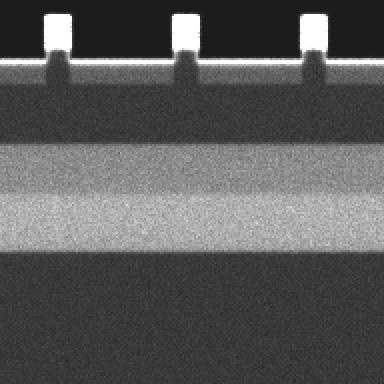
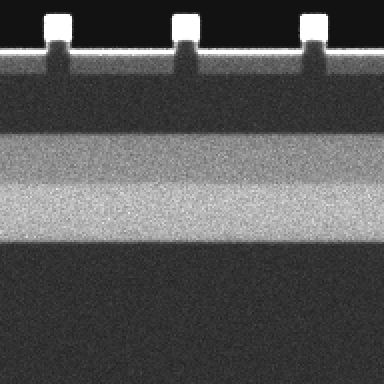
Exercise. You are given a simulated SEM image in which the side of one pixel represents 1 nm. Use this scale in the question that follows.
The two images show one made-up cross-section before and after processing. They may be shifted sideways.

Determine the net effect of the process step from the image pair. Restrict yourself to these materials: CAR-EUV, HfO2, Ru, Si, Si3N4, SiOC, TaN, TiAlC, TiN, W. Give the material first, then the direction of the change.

HfO2: removed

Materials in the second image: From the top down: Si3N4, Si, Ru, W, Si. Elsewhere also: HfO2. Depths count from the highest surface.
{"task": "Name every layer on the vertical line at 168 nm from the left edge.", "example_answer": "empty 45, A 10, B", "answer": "empty 34, Si3N4 24, Si 60, Ru 50, W 58, Si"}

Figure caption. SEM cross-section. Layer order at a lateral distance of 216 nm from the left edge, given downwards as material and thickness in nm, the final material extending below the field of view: empty 34, Si3N4 24, Si 60, Ru 50, W 58, Si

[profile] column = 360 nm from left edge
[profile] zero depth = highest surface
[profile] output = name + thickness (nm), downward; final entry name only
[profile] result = empty 34, Si3N4 24, Si 60, Ru 50, W 58, Si